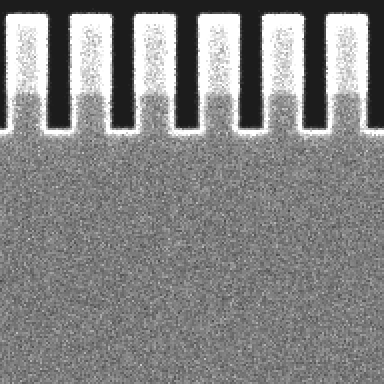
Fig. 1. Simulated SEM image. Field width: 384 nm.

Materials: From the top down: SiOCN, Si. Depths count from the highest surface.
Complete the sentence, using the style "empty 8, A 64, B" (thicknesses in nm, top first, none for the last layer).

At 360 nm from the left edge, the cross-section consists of SiOCN 78, Si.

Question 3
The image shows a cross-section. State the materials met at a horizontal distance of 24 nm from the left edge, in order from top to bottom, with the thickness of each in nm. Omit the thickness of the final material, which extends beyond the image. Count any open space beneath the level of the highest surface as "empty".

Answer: SiOCN 78, Si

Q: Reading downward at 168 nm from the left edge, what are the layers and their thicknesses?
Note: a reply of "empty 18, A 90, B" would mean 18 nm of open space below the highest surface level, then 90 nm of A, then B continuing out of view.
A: SiOCN 78, Si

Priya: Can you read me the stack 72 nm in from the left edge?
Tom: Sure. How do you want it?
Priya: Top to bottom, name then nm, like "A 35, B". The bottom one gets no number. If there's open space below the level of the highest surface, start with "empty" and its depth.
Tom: SiOCN 78, Si